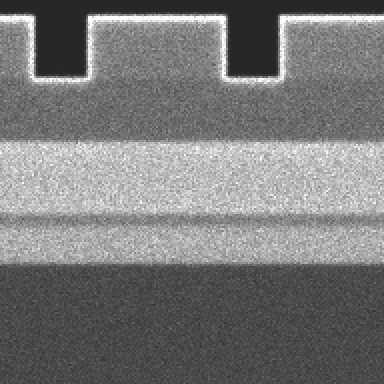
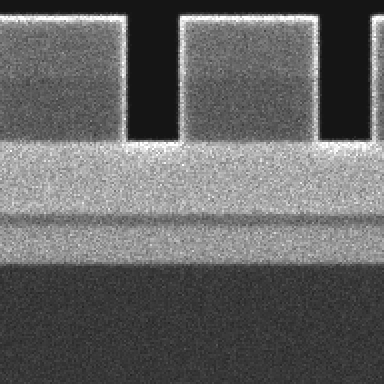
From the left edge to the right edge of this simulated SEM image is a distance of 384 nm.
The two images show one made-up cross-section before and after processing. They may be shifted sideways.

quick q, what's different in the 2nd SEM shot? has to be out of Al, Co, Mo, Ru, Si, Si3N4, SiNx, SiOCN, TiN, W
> SiNx removed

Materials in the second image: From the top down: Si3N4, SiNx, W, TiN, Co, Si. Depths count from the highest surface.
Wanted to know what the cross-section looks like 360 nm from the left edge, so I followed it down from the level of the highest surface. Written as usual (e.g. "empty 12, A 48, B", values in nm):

empty 126, W 72, TiN 12, Co 38, Si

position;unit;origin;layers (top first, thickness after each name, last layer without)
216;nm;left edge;Si3N4 62, SiNx 64, W 72, TiN 12, Co 38, Si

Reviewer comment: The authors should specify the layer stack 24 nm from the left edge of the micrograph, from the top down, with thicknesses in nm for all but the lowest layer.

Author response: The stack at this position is Si3N4 62, SiNx 64, W 72, TiN 12, Co 38, Si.